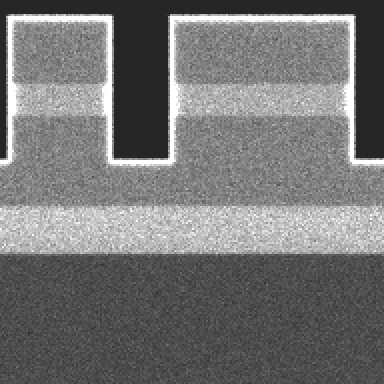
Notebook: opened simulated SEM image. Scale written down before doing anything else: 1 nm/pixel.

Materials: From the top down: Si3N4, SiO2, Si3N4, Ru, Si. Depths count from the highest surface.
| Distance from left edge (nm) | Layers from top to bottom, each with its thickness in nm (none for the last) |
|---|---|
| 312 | Si3N4 68, SiO2 32, Si3N4 90, Ru 48, Si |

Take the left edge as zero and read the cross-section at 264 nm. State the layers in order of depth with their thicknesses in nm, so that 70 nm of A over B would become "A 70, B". Si3N4 68, SiO2 32, Si3N4 90, Ru 48, Si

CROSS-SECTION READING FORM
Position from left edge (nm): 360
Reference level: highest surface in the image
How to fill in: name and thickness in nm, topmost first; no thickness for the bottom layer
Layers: empty 144, Si3N4 46, Ru 48, Si